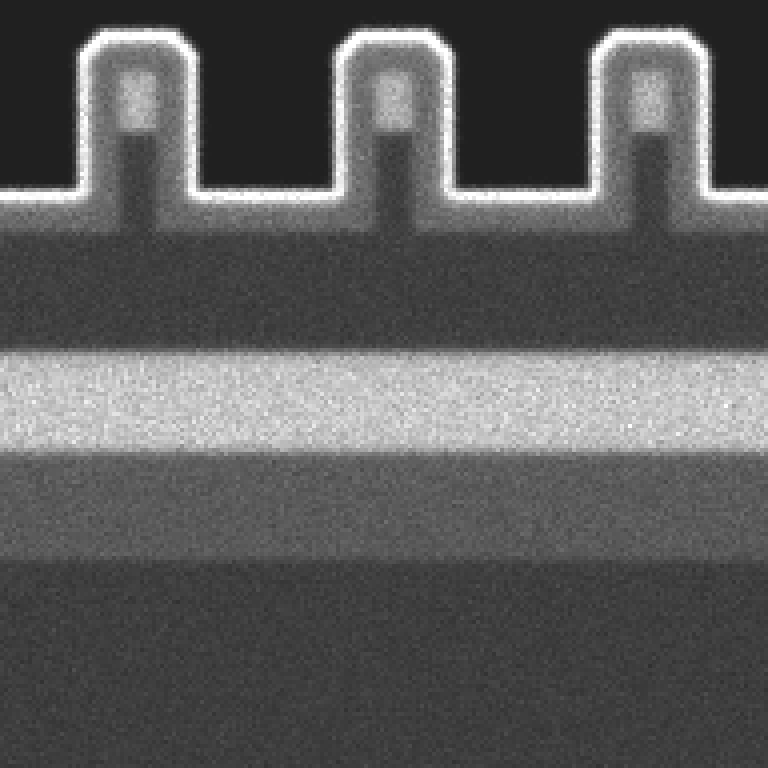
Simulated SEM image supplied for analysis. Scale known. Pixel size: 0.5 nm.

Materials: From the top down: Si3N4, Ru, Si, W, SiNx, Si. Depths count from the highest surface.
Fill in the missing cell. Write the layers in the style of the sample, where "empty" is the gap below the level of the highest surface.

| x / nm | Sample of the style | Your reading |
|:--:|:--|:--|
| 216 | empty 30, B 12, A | empty 2, Si3N4 98, Si 60, W 50, SiNx 54, Si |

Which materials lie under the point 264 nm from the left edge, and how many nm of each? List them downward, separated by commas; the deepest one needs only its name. empty 80, Si3N4 20, Si 60, W 50, SiNx 54, Si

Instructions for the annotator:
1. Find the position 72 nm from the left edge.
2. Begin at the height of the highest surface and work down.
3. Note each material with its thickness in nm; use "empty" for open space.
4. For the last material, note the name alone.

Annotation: Si3N4 20, Ru 30, Si 110, W 50, SiNx 54, Si